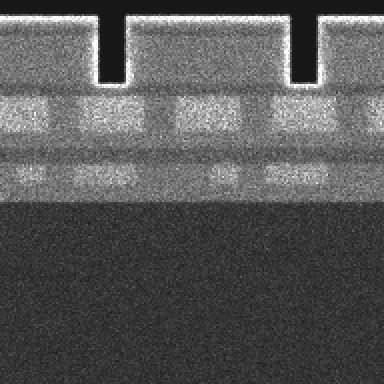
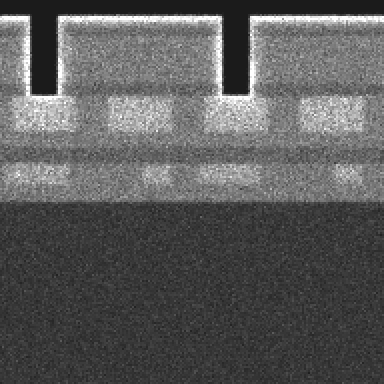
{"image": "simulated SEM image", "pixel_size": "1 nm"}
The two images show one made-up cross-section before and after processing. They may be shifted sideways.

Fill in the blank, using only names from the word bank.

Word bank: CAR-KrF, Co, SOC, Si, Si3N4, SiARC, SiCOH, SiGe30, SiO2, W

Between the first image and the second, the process removed Si3N4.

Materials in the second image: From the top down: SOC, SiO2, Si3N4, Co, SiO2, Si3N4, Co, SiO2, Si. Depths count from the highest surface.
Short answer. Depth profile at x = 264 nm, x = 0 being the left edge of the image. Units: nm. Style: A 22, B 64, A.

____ SOC 20, SiO2 48, Si3N4 12, Co 36, SiO2 16, Si3N4 16, SiO2 38, Si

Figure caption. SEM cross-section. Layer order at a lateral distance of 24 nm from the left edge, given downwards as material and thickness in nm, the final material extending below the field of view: SOC 20, SiO2 48, Si3N4 12, Co 36, SiO2 16, Si3N4 16, Co 20, SiO2 18, Si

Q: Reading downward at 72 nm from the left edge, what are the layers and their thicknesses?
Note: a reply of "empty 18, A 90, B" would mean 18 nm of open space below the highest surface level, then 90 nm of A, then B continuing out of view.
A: SOC 20, SiO2 48, Si3N4 12, Co 36, SiO2 16, Si3N4 16, SiO2 38, Si